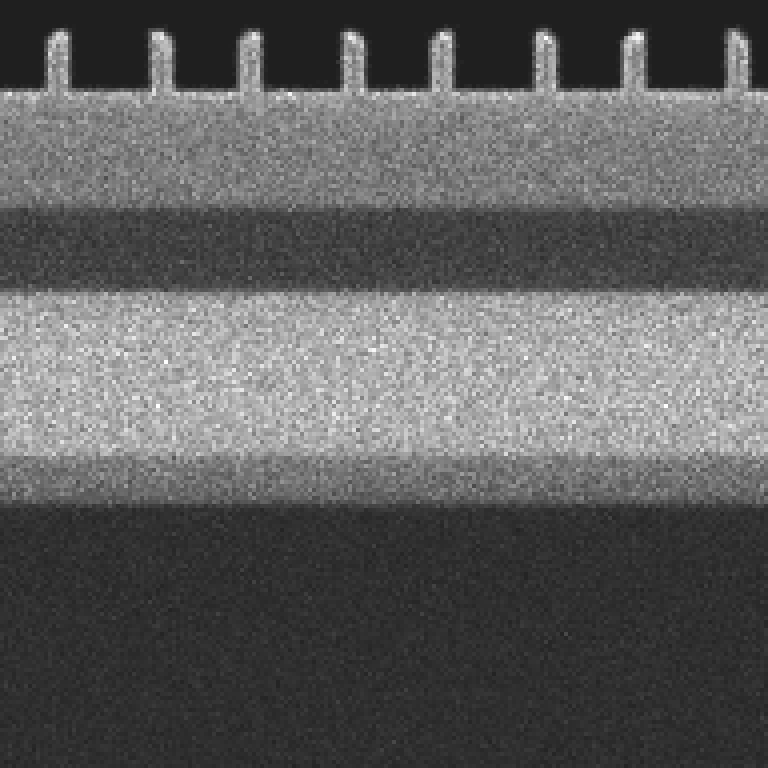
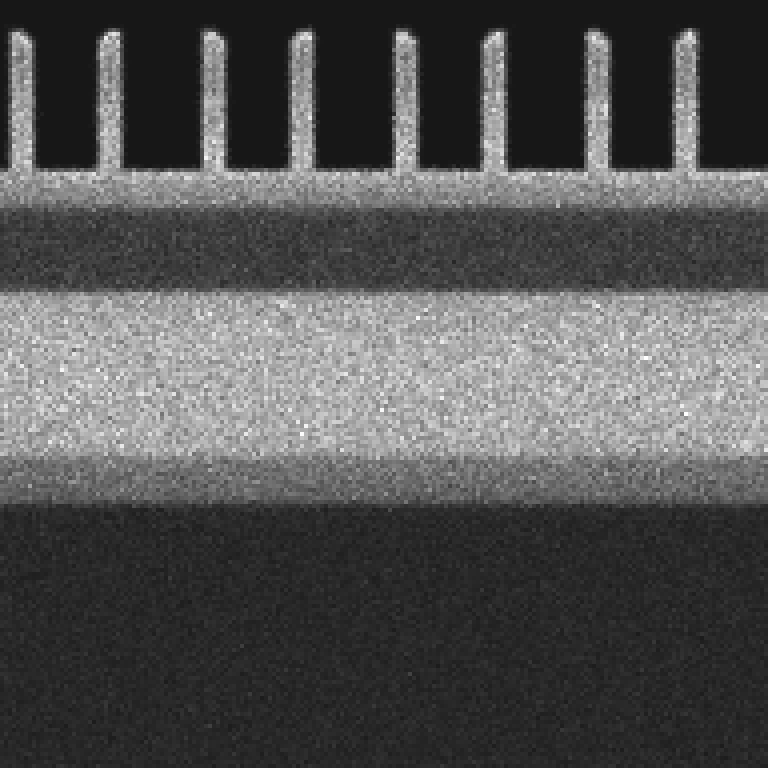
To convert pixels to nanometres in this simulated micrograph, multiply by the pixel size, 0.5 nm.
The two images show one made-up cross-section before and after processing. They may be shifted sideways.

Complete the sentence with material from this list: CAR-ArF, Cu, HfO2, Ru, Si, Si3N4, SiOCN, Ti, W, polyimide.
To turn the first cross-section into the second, W must be removed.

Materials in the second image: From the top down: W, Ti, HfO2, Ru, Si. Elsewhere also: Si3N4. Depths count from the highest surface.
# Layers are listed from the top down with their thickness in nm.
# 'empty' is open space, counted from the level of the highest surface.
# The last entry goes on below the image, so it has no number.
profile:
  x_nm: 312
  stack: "empty 70, W 18, Ti 42, HfO2 82, Ru 24, Si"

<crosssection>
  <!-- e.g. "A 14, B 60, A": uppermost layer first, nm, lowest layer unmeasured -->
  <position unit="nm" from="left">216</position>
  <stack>empty 70, W 18, Ti 42, HfO2 82, Ru 24, Si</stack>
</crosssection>